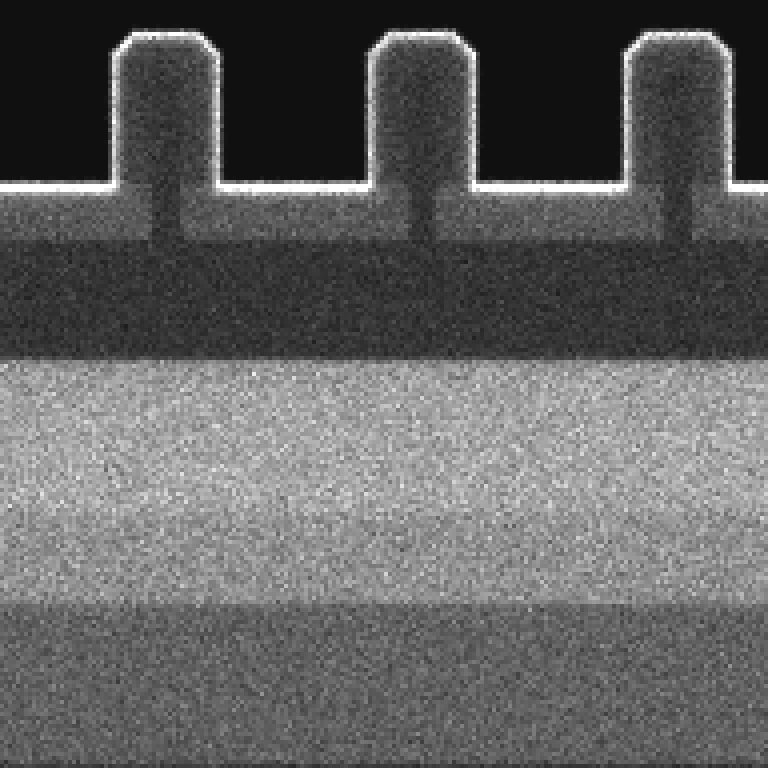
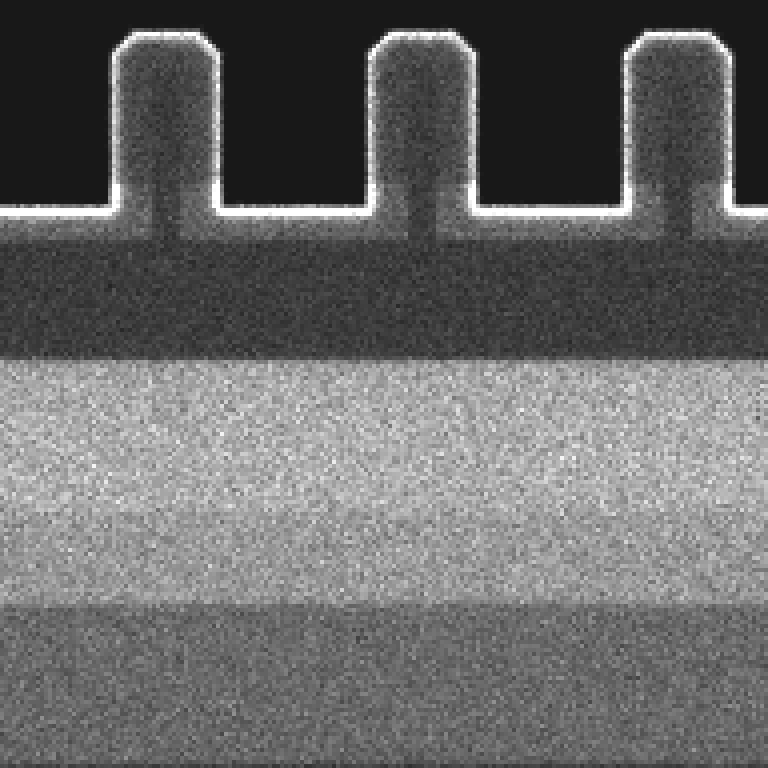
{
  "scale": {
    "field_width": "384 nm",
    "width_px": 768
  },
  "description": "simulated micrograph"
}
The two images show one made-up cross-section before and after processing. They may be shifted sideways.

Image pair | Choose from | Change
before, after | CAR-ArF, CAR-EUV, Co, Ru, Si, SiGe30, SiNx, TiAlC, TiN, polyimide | SiNx (removed)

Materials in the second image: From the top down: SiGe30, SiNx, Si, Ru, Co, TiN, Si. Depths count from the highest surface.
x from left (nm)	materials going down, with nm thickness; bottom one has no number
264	empty 88, SiNx 16, Si 60, Ru 76, Co 46, TiN 80, Si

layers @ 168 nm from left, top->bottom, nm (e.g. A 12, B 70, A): empty 88, SiNx 16, Si 60, Ru 76, Co 46, TiN 80, Si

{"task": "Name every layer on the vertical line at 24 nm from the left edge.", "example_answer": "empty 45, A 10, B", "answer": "empty 88, SiNx 16, Si 60, Ru 76, Co 46, TiN 80, Si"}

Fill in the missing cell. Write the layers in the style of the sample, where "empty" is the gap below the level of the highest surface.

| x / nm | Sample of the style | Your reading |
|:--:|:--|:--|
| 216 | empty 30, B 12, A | SiGe30 20, Si 144, Ru 76, Co 46, TiN 80, Si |